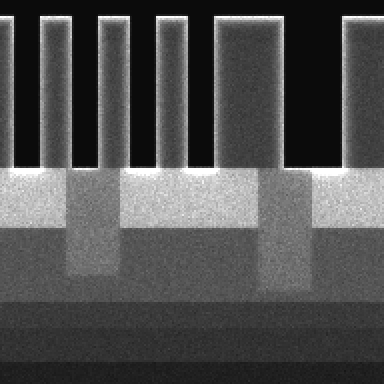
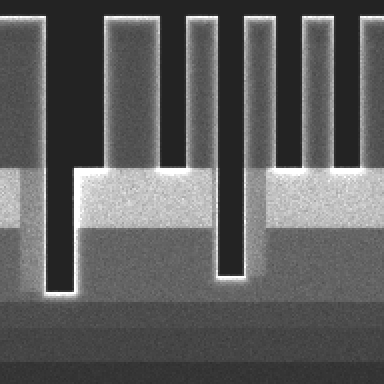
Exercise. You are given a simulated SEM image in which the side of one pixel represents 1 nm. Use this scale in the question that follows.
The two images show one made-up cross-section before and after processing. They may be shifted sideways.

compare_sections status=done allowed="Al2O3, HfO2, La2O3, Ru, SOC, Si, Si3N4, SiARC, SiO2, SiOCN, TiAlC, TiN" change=removed material="Ru"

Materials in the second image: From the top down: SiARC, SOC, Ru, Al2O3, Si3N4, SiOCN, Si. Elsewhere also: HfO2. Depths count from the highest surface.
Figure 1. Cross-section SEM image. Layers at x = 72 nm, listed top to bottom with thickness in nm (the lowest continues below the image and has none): empty 276, Al2O3 10, Si3N4 26, SiOCN 34, Si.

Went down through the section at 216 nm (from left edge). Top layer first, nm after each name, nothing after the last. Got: SiARC 26, SOC 126, Ru 108, Al2O3 26, Si3N4 26, SiOCN 34, Si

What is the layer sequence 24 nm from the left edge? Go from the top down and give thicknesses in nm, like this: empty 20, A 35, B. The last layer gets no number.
SiARC 26, SOC 126, Ru 124, Al2O3 10, Si3N4 26, SiOCN 34, Si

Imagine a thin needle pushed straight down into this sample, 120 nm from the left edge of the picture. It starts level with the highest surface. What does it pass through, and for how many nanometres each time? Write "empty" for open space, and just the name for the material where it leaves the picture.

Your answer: SiARC 26, SOC 126, HfO2 60, Al2O3 74, Si3N4 26, SiOCN 34, Si